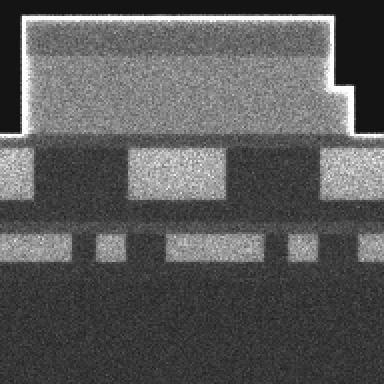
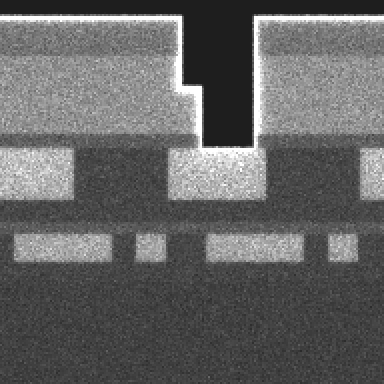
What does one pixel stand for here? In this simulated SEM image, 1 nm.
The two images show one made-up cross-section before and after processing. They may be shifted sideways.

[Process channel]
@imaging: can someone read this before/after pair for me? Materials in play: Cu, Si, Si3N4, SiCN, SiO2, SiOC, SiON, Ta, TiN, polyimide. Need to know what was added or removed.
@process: SiCN removed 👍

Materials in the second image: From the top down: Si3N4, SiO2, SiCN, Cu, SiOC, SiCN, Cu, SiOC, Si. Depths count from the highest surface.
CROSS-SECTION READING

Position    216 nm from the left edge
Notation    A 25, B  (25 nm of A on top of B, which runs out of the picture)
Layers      empty 132, Cu 52, SiOC 22, SiCN 12, Cu 28, SiOC 20, Si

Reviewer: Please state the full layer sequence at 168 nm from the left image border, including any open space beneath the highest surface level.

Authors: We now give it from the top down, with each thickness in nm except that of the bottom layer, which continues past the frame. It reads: Si3N4 40, SiO2 78, SiCN 14, Cu 52, SiOC 22, SiCN 12, SiOC 48, Si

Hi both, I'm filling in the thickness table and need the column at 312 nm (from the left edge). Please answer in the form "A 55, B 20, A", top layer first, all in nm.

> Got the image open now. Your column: Si3N4 40, SiO2 78, SiCN 14, SiOC 74, SiCN 12, SiOC 48, Si